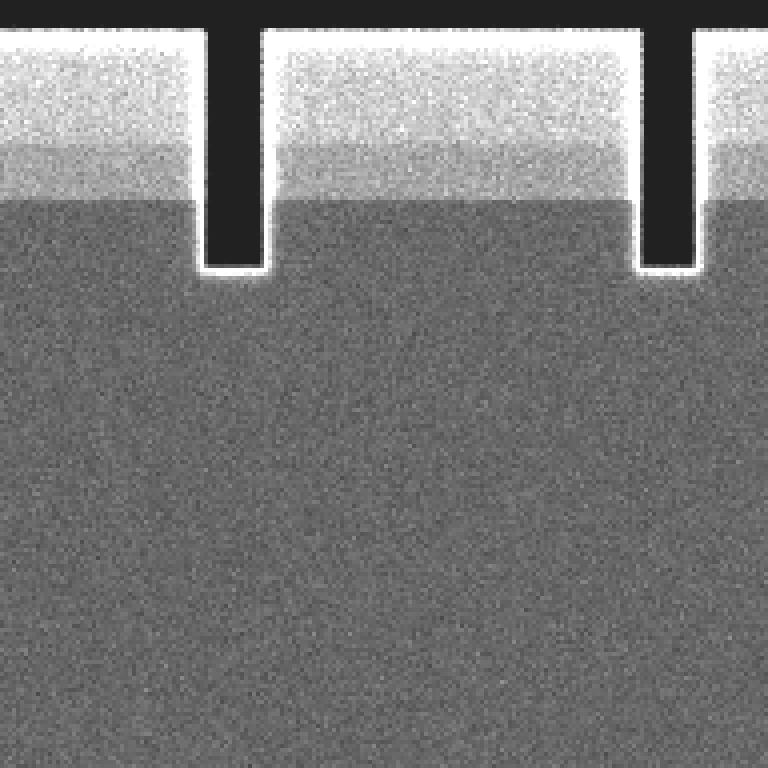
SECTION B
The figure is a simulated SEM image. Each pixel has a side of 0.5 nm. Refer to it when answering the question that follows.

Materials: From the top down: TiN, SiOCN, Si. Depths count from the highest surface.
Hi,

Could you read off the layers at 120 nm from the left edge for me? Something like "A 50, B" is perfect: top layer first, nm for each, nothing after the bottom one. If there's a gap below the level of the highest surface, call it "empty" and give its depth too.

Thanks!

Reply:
empty 118, Si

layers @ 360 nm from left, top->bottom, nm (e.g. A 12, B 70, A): TiN 56, SiOCN 28, Si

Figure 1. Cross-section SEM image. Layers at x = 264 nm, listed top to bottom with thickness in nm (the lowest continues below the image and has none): TiN 56, SiOCN 28, Si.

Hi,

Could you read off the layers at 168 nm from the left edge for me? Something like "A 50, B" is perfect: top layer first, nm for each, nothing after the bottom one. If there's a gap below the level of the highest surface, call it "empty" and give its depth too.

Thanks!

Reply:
TiN 56, SiOCN 28, Si